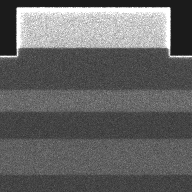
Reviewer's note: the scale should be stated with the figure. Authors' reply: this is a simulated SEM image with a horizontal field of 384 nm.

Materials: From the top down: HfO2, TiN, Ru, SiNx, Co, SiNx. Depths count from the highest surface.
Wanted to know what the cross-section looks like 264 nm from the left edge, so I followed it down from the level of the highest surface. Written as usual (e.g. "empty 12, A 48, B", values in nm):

HfO2 80, TiN 84, Ru 44, SiNx 54, Co 72, SiNx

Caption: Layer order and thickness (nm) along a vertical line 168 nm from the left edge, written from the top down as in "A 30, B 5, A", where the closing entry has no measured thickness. HfO2 80, TiN 84, Ru 44, SiNx 54, Co 72, SiNx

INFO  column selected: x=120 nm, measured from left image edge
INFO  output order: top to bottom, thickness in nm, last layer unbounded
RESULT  HfO2 80, TiN 84, Ru 44, SiNx 54, Co 72, SiNx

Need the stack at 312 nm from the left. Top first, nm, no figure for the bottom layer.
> HfO2 80, TiN 84, Ru 44, SiNx 54, Co 72, SiNx